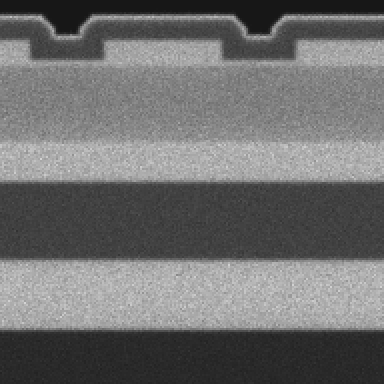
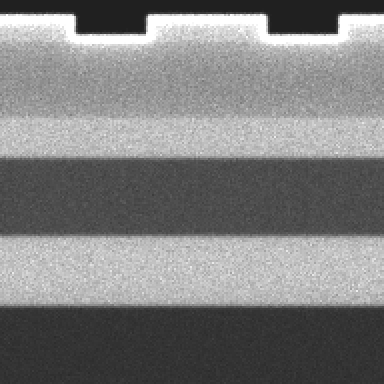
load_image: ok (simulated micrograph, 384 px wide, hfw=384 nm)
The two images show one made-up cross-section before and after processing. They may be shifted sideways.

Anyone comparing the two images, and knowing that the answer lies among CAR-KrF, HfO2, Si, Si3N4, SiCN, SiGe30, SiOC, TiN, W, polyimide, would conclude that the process removed TiN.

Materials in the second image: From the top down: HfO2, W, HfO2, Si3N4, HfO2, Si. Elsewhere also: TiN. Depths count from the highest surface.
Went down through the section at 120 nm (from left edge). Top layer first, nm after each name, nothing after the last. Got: empty 20, HfO2 6, W 76, HfO2 40, Si3N4 78, HfO2 70, Si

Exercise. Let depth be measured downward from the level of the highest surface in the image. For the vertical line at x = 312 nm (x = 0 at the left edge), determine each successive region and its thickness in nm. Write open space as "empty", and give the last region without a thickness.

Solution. empty 20, HfO2 6, W 76, HfO2 40, Si3N4 78, HfO2 70, Si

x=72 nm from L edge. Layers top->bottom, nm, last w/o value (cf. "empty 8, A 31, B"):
HfO2 26, W 76, HfO2 40, Si3N4 78, HfO2 70, Si